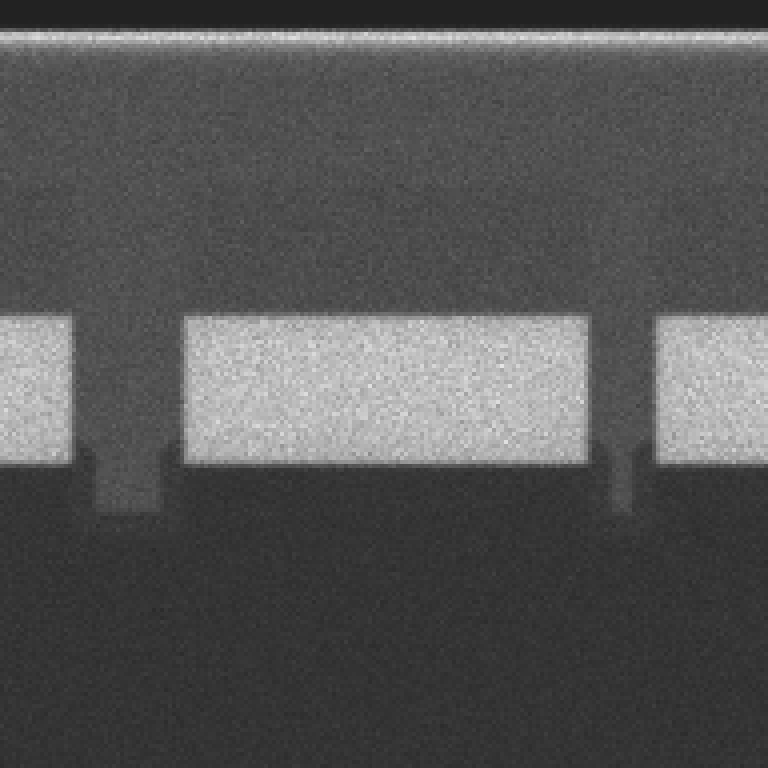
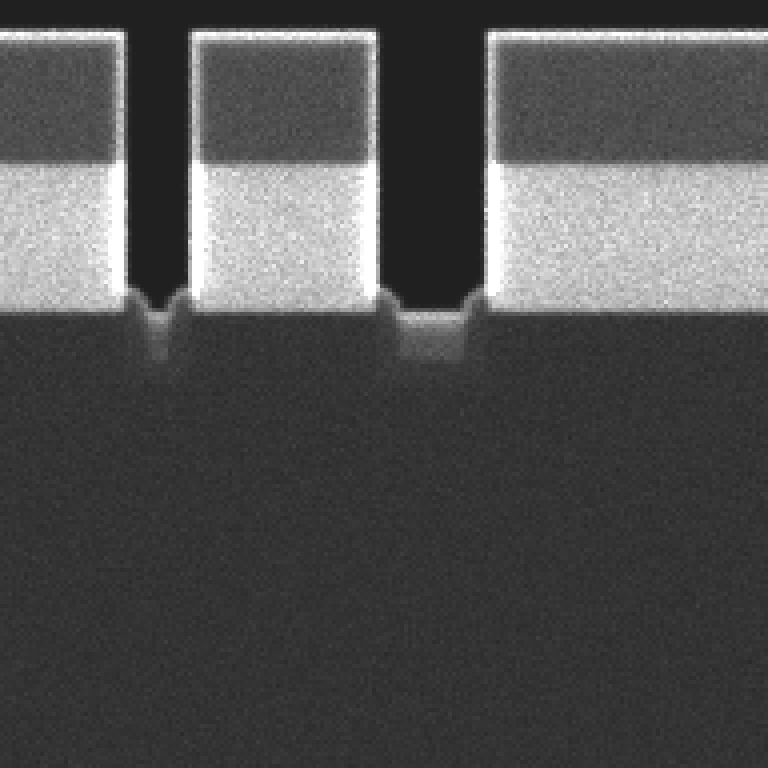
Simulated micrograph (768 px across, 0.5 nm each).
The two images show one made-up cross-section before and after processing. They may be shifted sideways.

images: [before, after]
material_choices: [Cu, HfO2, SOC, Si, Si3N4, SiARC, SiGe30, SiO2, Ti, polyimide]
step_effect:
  removed: SOC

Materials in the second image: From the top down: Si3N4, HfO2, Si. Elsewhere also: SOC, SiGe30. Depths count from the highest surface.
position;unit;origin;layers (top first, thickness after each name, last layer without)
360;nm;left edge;Si3N4 66, HfO2 74, Si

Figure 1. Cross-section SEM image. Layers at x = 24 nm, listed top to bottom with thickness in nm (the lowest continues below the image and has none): Si3N4 66, HfO2 74, Si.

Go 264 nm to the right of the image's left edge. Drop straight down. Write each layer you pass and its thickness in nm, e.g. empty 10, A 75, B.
Si3N4 66, HfO2 74, Si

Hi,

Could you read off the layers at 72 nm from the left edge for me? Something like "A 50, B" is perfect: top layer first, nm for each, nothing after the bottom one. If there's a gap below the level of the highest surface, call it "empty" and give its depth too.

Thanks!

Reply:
empty 134, SiGe30 42, Si